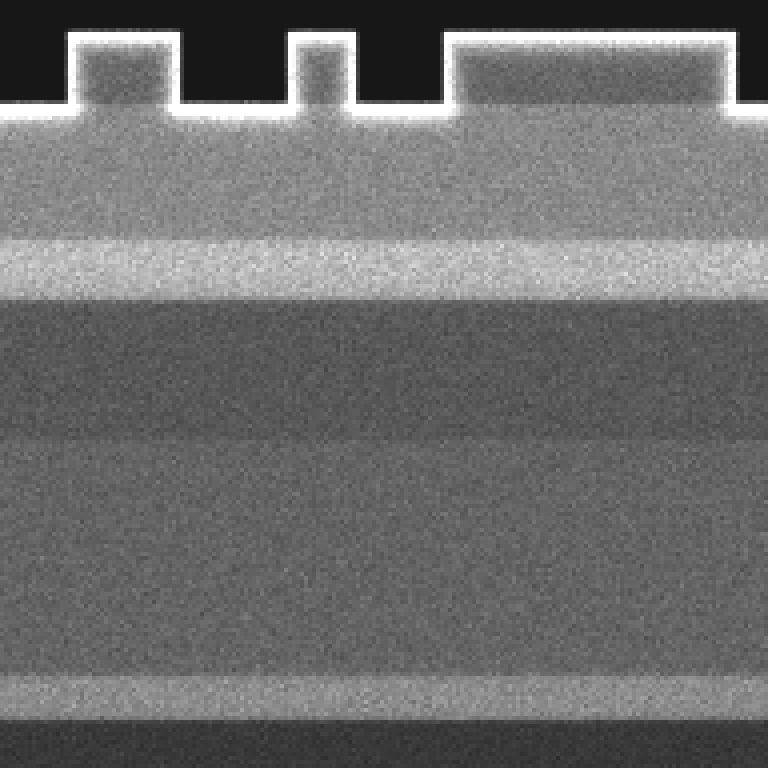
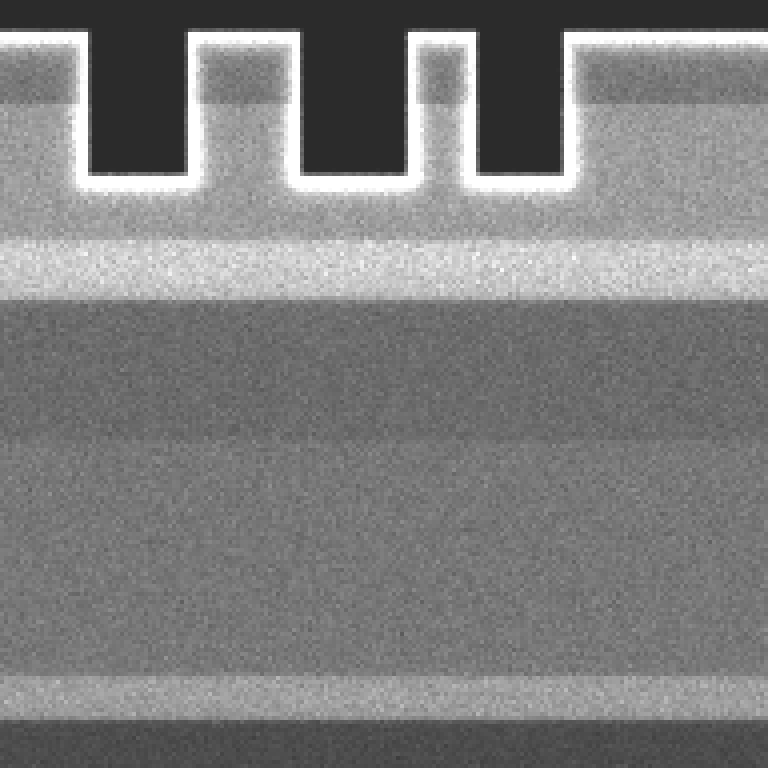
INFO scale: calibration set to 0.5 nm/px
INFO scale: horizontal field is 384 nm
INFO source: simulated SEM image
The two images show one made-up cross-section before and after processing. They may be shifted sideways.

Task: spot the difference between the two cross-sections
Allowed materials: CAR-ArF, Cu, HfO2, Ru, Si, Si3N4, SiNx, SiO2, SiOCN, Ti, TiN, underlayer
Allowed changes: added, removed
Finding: removed SiO2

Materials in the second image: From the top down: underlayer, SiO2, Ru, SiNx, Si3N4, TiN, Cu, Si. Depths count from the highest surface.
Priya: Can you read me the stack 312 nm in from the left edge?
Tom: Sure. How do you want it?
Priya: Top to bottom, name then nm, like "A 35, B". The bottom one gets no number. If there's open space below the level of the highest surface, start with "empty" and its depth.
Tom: underlayer 36, SiO2 68, Ru 30, SiNx 70, Si3N4 76, TiN 42, Cu 22, Si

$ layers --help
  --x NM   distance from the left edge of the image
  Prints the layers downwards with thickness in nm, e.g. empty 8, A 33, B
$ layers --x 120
underlayer 36, SiO2 68, Ru 30, SiNx 70, Si3N4 76, TiN 42, Cu 22, Si